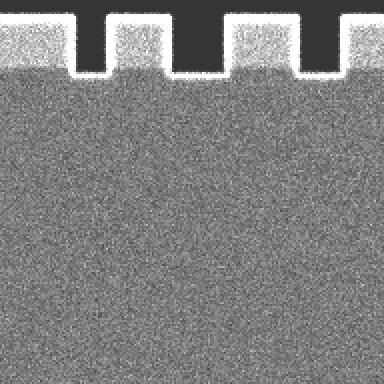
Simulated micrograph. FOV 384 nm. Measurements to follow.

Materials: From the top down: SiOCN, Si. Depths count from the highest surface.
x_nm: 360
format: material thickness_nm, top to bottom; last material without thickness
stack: SiOCN 52, Si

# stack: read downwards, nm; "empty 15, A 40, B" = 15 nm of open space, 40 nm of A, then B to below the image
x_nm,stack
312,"empty 58, Si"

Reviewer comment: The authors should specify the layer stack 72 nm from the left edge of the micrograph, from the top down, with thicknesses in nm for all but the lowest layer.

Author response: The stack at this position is SiOCN 52, Si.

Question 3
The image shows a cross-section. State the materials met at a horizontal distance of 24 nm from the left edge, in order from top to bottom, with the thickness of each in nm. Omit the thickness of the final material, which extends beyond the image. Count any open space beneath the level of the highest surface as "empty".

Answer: SiOCN 52, Si